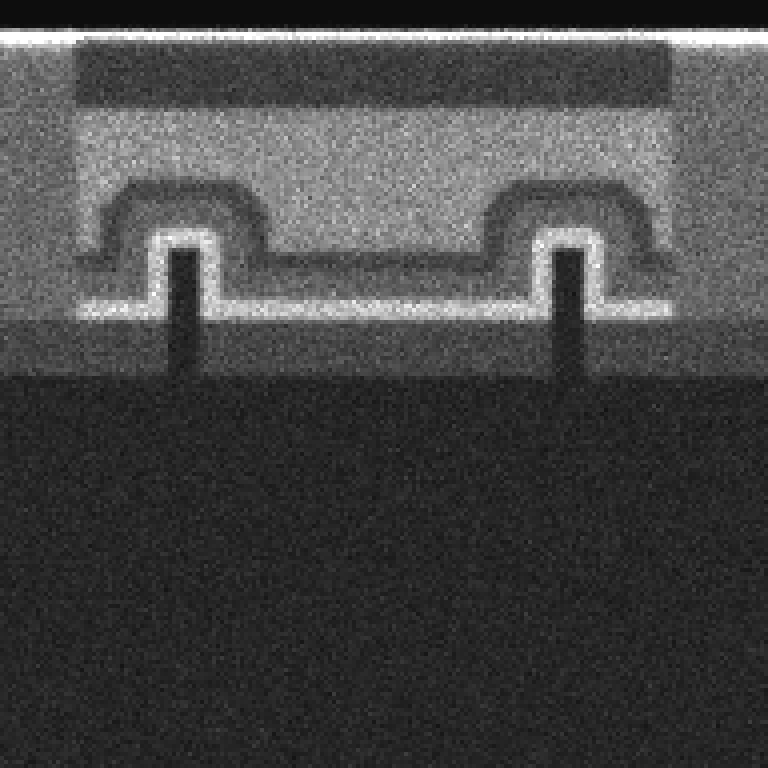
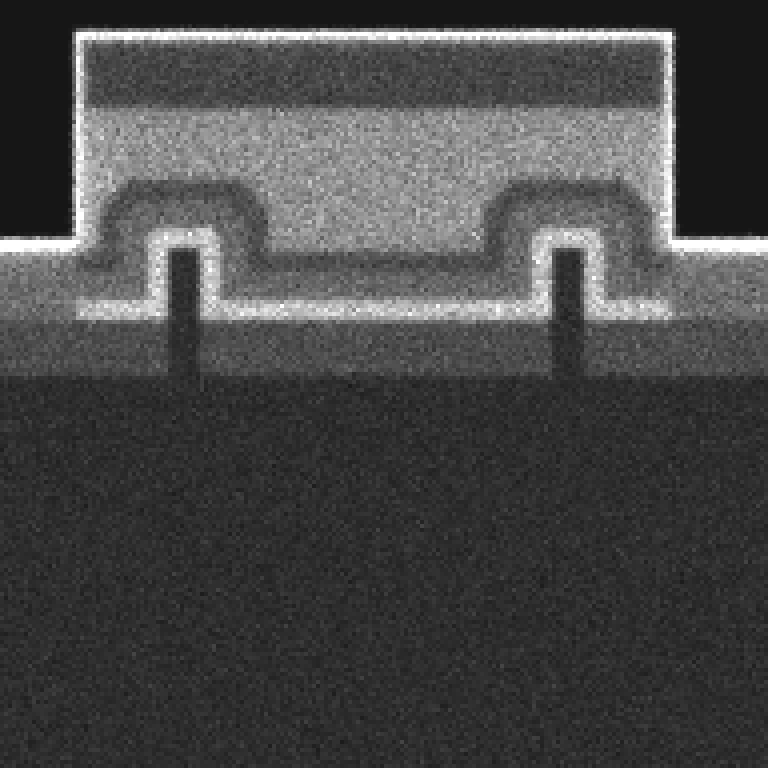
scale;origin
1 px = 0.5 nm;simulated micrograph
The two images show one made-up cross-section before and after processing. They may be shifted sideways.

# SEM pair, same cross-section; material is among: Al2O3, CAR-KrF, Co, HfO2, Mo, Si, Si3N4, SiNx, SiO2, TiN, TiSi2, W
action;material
removed;Al2O3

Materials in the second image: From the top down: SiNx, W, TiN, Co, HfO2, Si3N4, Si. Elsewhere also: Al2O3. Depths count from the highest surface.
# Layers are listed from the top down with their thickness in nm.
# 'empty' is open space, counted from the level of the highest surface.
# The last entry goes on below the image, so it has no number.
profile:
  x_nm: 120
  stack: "SiNx 38, W 38, TiN 16, Co 42, HfO2 10, Si3N4 28, Si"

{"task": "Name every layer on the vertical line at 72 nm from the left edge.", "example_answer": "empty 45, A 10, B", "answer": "SiNx 38, W 36, TiN 10, Co 50, HfO2 10, Si3N4 28, Si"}